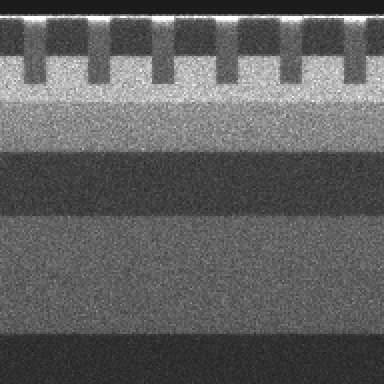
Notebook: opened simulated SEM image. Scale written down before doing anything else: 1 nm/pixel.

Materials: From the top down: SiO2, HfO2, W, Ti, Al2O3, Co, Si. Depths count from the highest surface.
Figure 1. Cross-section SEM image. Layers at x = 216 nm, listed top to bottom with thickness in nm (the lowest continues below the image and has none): SiO2 68, HfO2 18, W 50, Ti 64, Al2O3 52, Co 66, Si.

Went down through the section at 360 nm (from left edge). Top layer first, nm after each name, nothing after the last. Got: SiO2 68, HfO2 18, W 50, Ti 64, Al2O3 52, Co 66, Si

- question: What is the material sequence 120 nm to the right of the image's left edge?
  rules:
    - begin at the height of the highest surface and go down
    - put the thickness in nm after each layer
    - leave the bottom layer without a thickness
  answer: Ti 40, HfO2 46, W 50, Ti 64, Al2O3 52, Co 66, Si